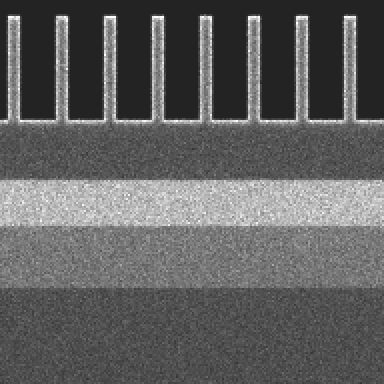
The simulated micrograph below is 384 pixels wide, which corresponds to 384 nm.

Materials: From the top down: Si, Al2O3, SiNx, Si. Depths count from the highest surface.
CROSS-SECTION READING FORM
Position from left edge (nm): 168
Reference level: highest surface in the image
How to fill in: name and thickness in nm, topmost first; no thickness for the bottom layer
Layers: empty 104, Si 60, Al2O3 46, SiNx 62, Si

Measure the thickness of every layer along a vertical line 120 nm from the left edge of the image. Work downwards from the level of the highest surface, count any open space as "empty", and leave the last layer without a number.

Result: empty 104, Si 60, Al2O3 46, SiNx 62, Si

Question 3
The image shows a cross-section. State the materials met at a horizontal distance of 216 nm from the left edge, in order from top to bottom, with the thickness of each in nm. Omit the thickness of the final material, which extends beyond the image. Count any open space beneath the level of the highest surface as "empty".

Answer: empty 104, Si 60, Al2O3 46, SiNx 62, Si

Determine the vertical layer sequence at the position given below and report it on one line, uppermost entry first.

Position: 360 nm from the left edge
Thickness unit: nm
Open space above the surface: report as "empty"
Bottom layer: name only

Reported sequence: empty 104, Si 60, Al2O3 46, SiNx 62, Si